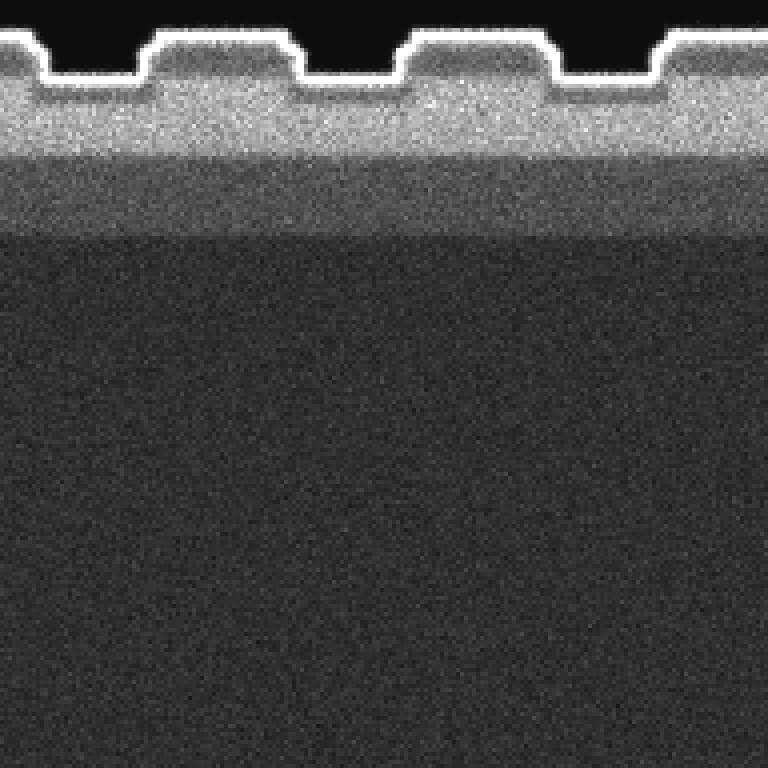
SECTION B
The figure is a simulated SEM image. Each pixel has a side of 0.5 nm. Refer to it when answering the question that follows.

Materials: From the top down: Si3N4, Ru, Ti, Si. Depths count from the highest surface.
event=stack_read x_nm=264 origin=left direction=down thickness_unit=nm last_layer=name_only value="Si3N4 22, Ru 40, Ti 40, Si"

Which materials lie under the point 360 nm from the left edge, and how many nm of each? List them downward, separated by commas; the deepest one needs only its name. Si3N4 22, Ru 40, Ti 40, Si